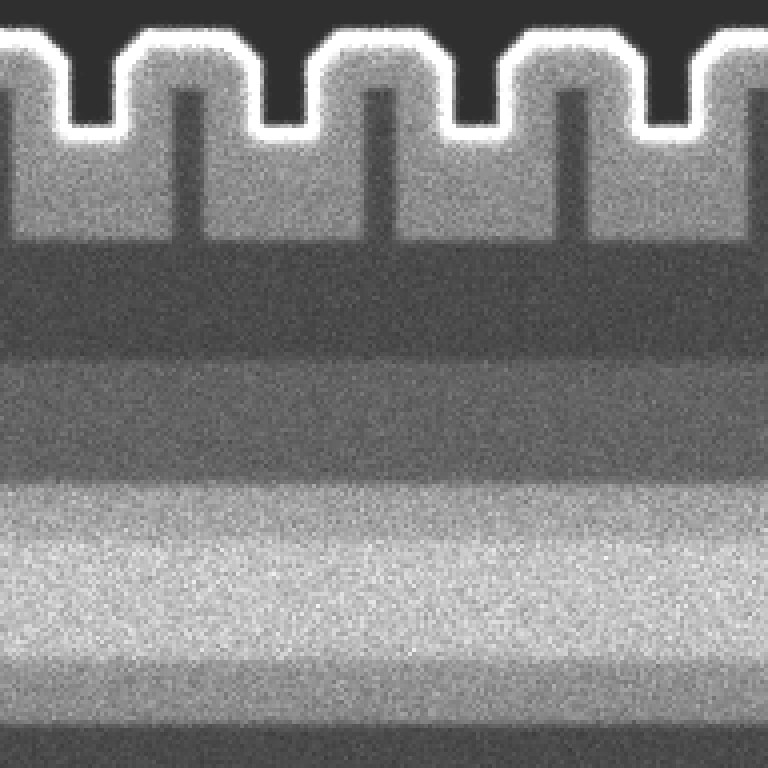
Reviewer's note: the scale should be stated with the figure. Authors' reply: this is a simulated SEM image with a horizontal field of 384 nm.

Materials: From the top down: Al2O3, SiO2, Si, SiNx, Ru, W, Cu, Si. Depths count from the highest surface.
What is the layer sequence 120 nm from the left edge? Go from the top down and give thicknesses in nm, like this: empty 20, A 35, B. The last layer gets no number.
empty 6, Al2O3 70, SiO2 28, Si 60, SiNx 62, Ru 28, W 60, Cu 32, Si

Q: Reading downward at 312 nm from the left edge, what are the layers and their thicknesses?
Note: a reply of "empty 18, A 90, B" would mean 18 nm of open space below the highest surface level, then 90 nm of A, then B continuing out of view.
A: empty 6, Al2O3 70, SiO2 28, Si 60, SiNx 62, Ru 28, W 60, Cu 32, Si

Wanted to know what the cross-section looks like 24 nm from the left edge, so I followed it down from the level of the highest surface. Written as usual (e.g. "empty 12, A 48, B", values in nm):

empty 6, Al2O3 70, SiO2 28, Si 60, SiNx 62, Ru 28, W 60, Cu 32, Si